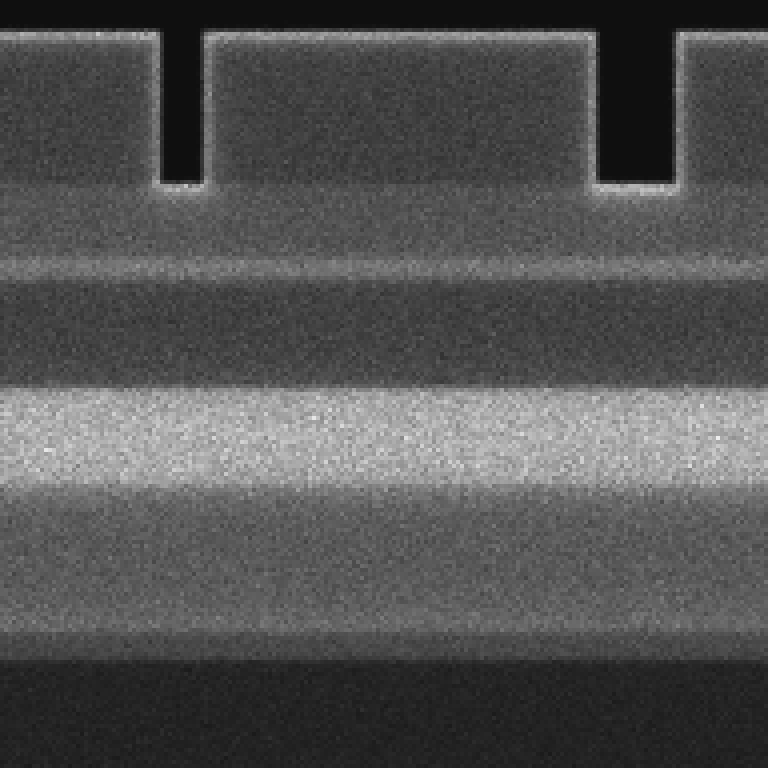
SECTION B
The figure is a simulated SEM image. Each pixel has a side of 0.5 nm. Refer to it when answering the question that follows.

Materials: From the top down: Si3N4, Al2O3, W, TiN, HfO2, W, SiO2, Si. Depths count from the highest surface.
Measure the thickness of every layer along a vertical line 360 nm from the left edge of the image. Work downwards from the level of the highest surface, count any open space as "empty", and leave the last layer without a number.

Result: Si3N4 76, Al2O3 38, W 10, TiN 54, HfO2 48, W 74, SiO2 14, Si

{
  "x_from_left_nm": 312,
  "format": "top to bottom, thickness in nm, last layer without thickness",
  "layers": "empty 76, Al2O3 38, W 10, TiN 54, HfO2 48, W 74, SiO2 14, Si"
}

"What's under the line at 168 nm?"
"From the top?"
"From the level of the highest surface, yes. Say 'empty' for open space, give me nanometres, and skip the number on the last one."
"Si3N4 76, Al2O3 38, W 10, TiN 54, HfO2 48, W 74, SiO2 14, Si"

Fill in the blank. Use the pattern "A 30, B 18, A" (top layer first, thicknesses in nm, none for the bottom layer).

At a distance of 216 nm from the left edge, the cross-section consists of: Si3N4 76, Al2O3 38, W 10, TiN 54, HfO2 48, W 74, SiO2 14, Si